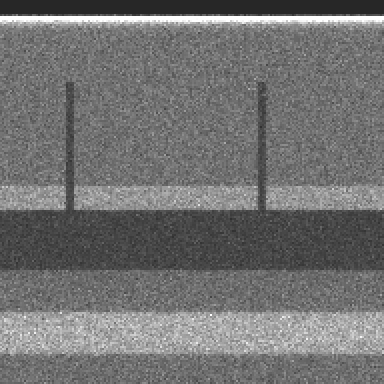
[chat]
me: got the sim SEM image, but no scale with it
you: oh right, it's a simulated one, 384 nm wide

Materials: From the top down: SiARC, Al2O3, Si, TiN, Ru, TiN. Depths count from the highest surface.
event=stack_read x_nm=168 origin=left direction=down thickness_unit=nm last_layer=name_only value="SiARC 170, Al2O3 24, Si 60, TiN 42, Ru 42, TiN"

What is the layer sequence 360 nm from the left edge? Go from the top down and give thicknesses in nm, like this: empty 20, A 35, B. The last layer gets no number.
SiARC 170, Al2O3 24, Si 60, TiN 42, Ru 42, TiN